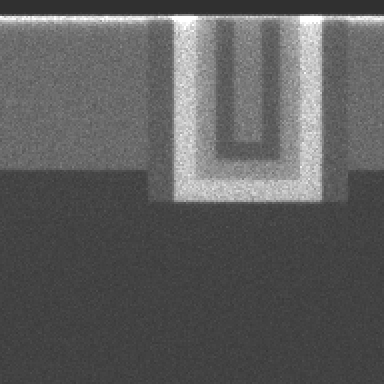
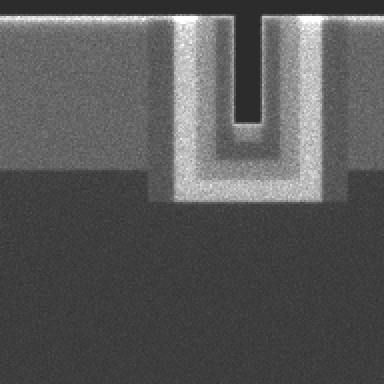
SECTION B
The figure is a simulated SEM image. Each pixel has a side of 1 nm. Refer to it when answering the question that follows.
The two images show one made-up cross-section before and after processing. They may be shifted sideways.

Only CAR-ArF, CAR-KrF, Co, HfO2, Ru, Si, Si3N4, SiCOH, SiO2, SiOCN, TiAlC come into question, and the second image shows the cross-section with Co removed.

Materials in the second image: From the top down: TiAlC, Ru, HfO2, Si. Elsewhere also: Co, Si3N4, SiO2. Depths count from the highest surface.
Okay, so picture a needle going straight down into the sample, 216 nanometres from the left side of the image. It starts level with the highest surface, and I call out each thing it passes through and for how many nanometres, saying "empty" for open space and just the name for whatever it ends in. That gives TiAlC 144, Ru 20, HfO2 22, Si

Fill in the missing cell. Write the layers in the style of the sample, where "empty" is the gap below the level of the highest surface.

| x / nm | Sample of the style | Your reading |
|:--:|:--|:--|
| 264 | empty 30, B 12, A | TiAlC 144, Ru 20, HfO2 22, Si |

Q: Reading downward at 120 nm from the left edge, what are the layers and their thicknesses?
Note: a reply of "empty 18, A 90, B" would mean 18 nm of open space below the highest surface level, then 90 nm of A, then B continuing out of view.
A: SiO2 154, Si